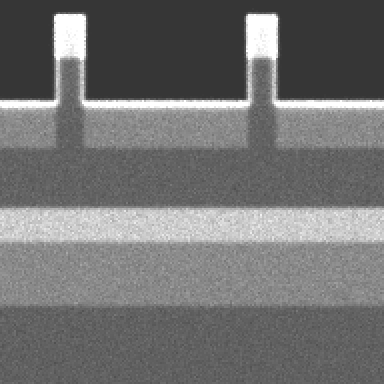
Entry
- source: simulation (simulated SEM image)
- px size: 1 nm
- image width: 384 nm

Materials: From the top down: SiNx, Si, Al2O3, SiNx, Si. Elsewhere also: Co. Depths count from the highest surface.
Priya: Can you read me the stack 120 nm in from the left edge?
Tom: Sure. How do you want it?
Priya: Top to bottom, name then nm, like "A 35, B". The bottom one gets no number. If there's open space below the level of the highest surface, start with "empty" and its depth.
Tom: empty 86, SiNx 46, Si 60, Al2O3 34, SiNx 64, Si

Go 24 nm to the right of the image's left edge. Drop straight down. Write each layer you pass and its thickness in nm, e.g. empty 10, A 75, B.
empty 86, SiNx 46, Si 60, Al2O3 34, SiNx 64, Si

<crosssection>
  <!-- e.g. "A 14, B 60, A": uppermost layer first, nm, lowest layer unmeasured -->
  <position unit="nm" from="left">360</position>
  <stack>empty 86, SiNx 46, Si 60, Al2O3 34, SiNx 64, Si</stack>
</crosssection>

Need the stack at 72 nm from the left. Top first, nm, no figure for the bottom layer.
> Co 42, Si 150, Al2O3 34, SiNx 64, Si